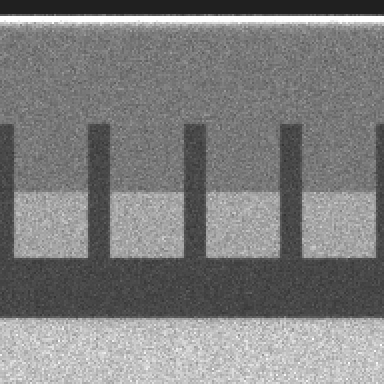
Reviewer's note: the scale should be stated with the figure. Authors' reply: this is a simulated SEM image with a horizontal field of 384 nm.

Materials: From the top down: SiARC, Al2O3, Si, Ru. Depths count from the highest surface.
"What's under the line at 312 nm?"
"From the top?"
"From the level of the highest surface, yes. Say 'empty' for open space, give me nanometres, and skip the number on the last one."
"SiARC 176, Al2O3 66, Si 60, Ru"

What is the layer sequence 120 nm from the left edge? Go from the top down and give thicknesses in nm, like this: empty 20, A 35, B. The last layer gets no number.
SiARC 176, Al2O3 66, Si 60, Ru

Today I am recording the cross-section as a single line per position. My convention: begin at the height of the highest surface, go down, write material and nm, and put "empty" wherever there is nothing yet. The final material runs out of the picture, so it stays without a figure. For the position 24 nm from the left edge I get SiARC 176, Al2O3 66, Si 60, Ru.